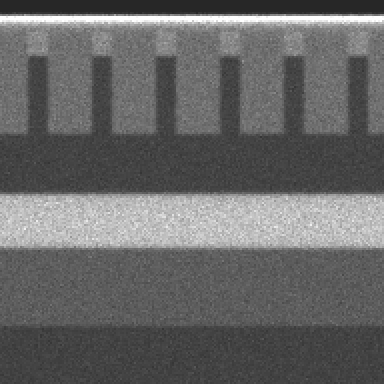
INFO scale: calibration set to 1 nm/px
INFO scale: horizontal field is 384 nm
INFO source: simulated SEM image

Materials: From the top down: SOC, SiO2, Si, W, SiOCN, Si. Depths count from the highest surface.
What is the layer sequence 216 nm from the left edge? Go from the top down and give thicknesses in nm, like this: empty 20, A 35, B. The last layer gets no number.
SOC 118, Si 60, W 54, SiOCN 78, Si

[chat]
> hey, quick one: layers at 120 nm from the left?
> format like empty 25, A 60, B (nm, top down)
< SOC 118, Si 60, W 54, SiOCN 78, Si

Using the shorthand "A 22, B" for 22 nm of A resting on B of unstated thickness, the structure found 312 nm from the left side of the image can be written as SOC 118, Si 60, W 54, SiOCN 78, Si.